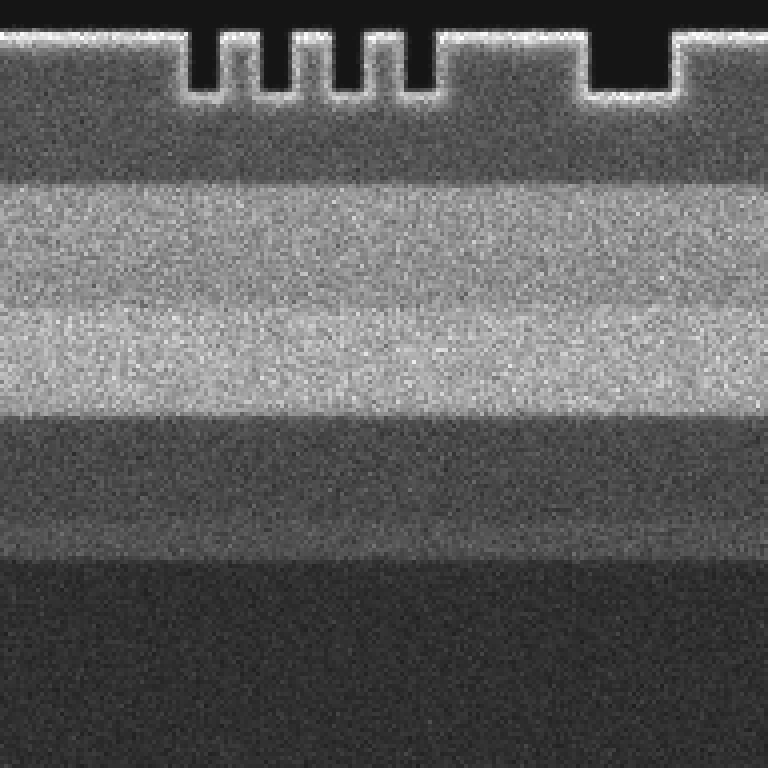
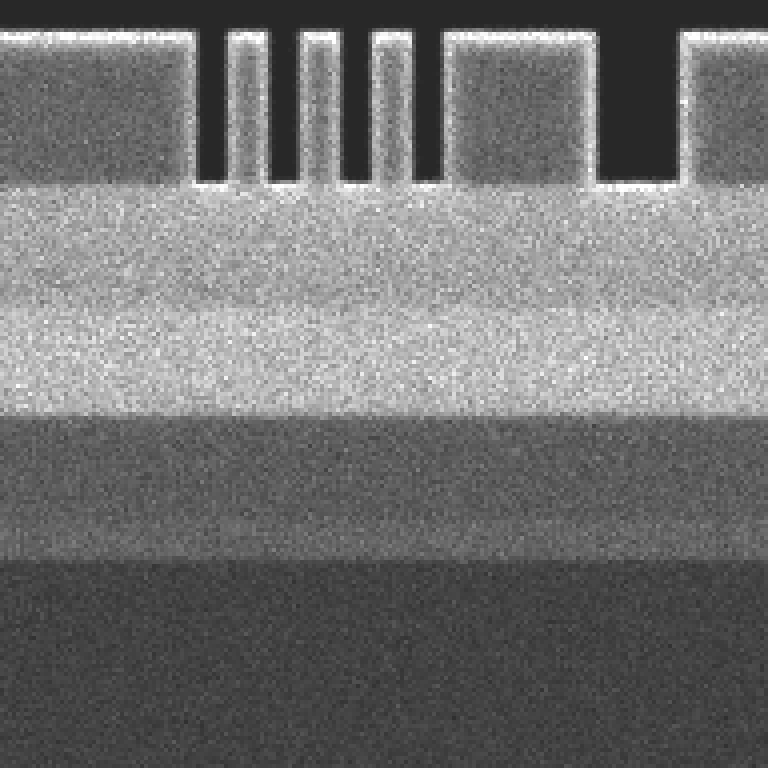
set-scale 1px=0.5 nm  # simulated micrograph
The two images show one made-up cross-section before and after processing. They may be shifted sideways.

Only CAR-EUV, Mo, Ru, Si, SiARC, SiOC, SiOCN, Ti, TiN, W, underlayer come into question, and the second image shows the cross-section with underlayer removed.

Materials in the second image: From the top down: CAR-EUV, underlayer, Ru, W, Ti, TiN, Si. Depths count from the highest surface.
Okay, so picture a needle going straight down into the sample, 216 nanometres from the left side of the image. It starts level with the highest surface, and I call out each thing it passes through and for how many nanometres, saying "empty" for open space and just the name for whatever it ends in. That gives empty 76, Ru 62, W 54, Ti 52, TiN 20, Si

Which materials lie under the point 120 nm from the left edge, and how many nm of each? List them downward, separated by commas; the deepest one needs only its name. CAR-EUV 30, underlayer 46, Ru 62, W 54, Ti 52, TiN 20, Si